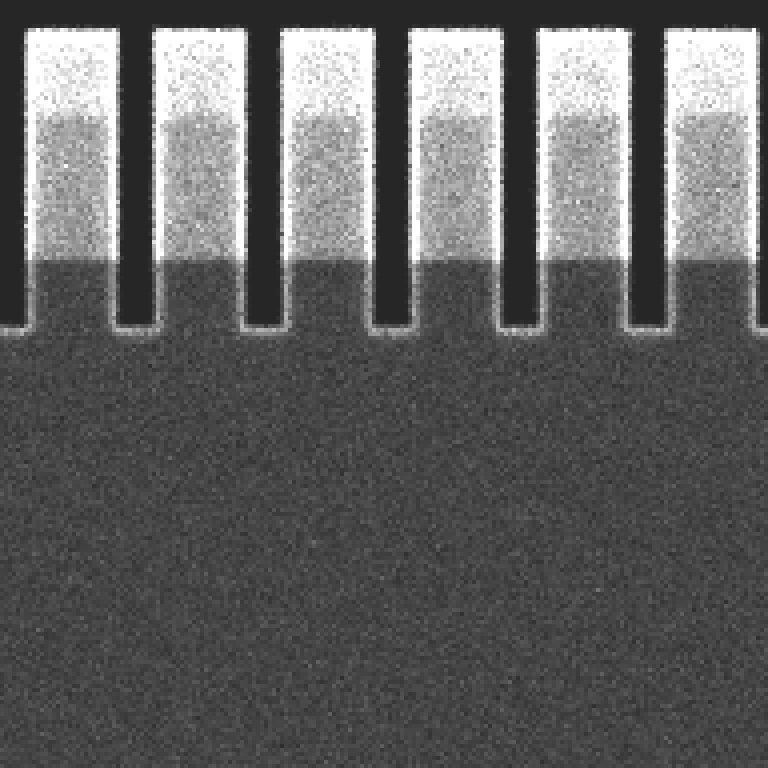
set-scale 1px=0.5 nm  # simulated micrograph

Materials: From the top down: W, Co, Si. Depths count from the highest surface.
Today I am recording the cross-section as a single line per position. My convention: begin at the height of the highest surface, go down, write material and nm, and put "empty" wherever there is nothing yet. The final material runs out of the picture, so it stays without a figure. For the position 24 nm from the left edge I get W 42, Co 72, Si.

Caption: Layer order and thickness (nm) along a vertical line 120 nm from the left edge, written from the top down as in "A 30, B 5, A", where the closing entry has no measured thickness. W 42, Co 72, Si